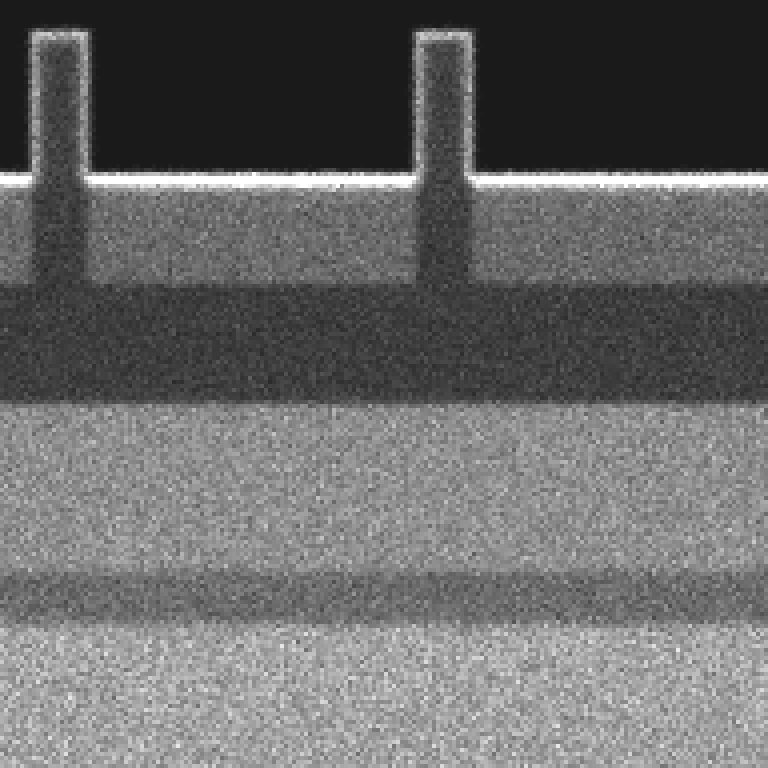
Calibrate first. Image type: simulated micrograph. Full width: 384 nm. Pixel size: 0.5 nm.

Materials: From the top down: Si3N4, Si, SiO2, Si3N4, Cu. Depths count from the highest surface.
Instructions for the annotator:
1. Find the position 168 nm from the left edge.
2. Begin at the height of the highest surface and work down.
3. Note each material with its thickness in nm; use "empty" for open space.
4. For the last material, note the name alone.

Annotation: empty 72, Si3N4 54, Si 60, SiO2 84, Si3N4 26, Cu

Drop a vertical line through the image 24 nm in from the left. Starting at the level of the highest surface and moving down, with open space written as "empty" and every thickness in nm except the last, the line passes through Si 186, SiO2 84, Si3N4 26, Cu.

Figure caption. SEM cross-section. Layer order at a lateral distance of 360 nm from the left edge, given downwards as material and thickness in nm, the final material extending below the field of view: empty 72, Si3N4 54, Si 60, SiO2 84, Si3N4 26, Cu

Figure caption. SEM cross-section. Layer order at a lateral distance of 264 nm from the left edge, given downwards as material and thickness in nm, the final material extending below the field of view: empty 72, Si3N4 54, Si 60, SiO2 84, Si3N4 26, Cu